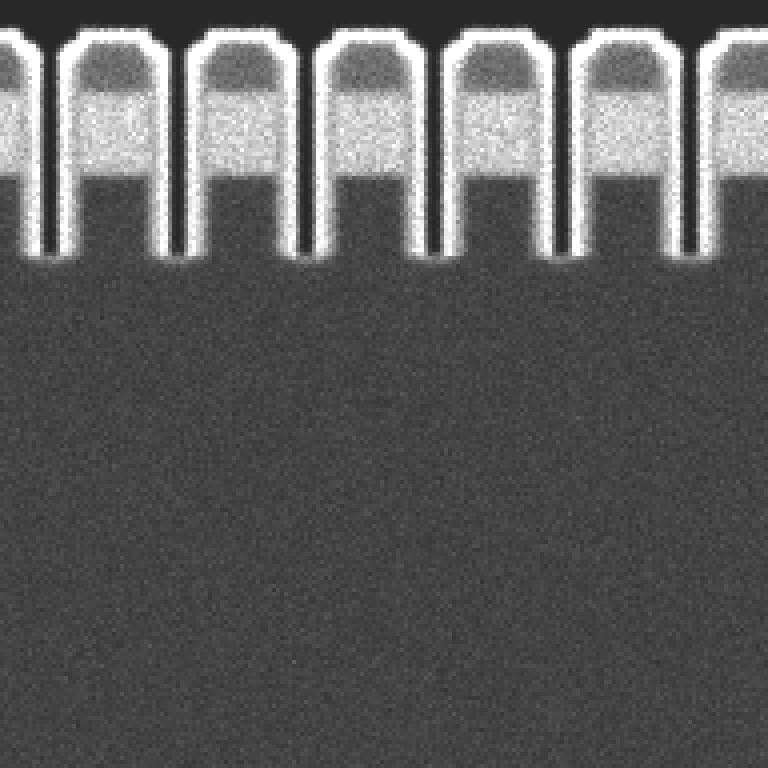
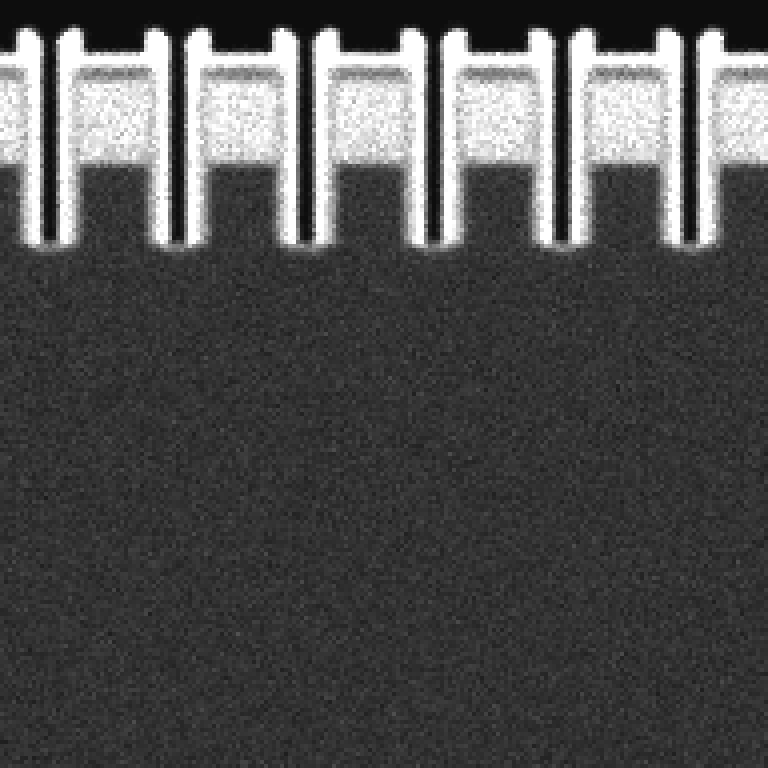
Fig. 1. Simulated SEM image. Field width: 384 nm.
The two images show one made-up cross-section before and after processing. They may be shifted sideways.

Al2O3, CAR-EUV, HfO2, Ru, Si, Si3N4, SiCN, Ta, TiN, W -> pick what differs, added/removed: Si3N4 removed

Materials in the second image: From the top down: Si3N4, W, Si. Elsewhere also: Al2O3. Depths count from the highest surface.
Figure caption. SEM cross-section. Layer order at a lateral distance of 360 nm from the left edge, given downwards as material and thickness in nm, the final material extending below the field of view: empty 12, Si3N4 12, W 42, Si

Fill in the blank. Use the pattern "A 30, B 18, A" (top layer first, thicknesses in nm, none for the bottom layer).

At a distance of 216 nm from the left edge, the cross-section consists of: empty 106, Si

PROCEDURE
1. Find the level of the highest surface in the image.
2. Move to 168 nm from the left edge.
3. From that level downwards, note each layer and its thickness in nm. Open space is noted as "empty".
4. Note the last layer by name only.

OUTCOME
empty 12, Si3N4 12, W 42, Si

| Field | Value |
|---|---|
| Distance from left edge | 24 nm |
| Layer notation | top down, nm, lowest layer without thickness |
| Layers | empty 106, Si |